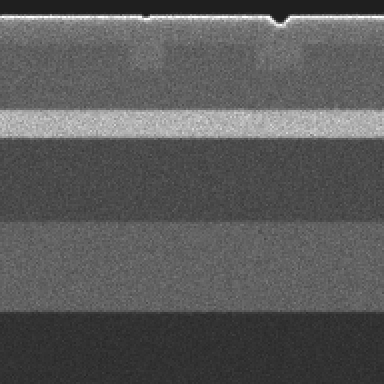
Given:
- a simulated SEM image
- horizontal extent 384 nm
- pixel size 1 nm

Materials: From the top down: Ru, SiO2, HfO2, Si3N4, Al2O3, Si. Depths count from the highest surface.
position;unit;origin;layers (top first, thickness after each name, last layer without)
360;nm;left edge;Ru 28, SiO2 66, HfO2 28, Si3N4 84, Al2O3 90, Si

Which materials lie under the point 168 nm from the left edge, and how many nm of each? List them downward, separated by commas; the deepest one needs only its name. Ru 28, SiO2 66, HfO2 28, Si3N4 84, Al2O3 90, Si